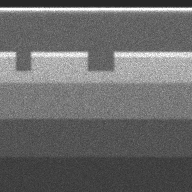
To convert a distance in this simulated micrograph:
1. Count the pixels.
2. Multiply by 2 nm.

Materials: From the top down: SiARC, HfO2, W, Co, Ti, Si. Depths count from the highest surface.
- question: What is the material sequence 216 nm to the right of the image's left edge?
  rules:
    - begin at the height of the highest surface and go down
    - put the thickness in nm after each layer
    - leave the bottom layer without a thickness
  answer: SiARC 126, W 24, Co 72, Ti 76, Si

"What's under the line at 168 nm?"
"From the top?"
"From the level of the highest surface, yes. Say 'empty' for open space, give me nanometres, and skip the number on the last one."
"SiARC 88, HfO2 10, W 52, Co 72, Ti 76, Si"